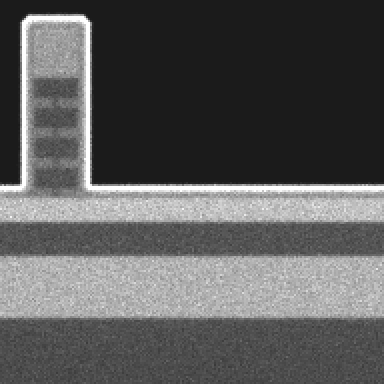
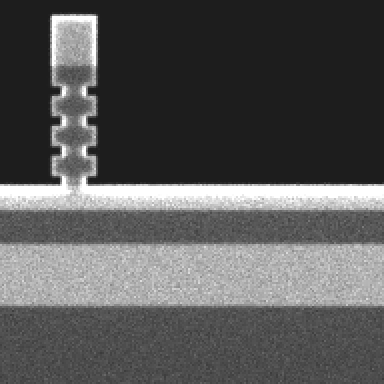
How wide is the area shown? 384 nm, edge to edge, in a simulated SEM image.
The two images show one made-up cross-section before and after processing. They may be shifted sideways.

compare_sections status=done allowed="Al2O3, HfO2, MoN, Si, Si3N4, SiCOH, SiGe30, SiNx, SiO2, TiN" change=removed material="SiNx"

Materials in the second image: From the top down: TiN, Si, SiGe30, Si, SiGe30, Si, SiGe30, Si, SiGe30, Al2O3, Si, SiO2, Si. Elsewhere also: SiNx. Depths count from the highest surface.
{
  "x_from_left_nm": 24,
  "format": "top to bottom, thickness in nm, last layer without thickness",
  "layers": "empty 170, Al2O3 24, Si 34, SiO2 62, Si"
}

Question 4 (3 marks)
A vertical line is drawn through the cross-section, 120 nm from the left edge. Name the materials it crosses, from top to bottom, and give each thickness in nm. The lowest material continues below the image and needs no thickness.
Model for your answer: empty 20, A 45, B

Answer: empty 170, Al2O3 24, Si 34, SiO2 62, Si